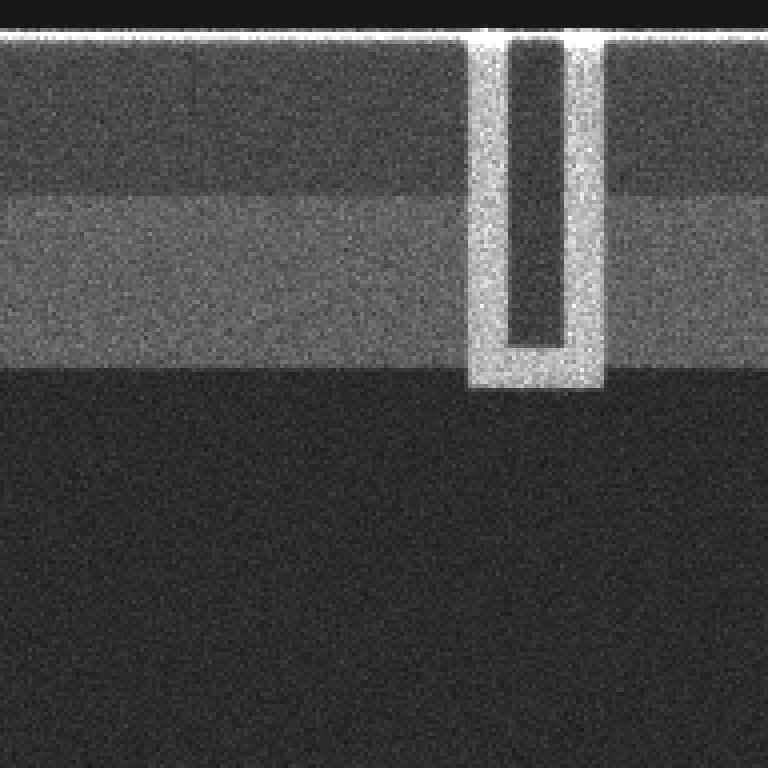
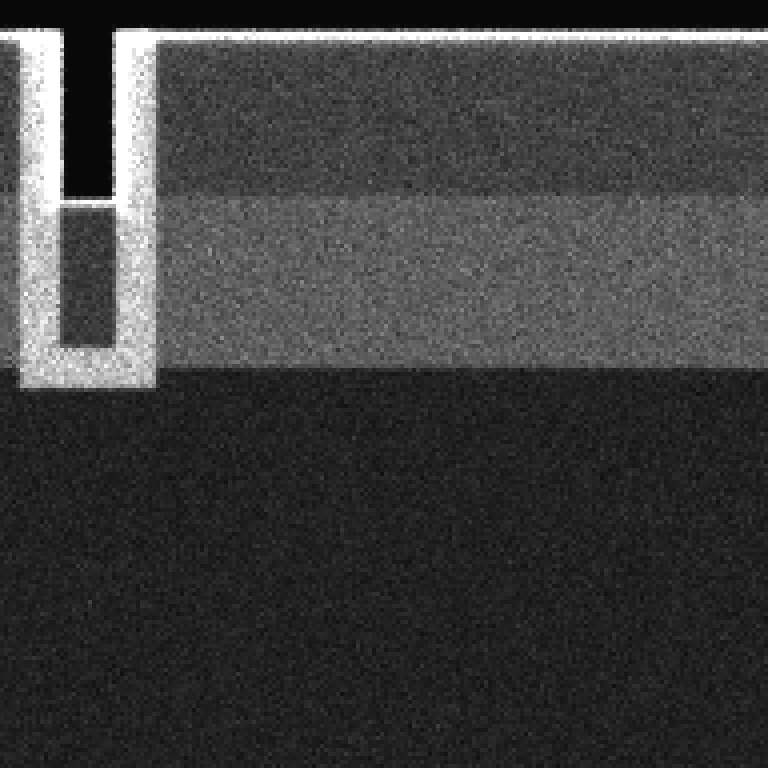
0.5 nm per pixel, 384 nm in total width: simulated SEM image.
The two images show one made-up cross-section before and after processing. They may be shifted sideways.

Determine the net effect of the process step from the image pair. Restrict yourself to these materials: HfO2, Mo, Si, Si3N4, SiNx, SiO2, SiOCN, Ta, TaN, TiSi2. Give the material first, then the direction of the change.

SiNx: removed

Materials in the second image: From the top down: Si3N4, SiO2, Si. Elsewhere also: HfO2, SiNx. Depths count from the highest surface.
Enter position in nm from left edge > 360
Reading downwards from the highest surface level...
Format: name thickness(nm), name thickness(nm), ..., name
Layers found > Si3N4 82, SiO2 86, Si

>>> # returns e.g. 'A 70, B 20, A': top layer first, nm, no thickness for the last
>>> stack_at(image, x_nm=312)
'Si3N4 82, SiO2 86, Si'